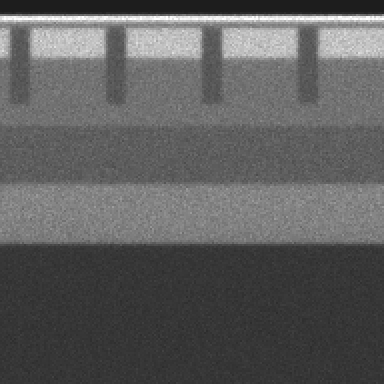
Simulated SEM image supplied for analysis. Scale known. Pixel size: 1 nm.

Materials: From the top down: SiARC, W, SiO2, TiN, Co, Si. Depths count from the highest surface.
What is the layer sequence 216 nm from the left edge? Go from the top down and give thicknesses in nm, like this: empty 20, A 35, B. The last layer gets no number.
SiARC 88, SiO2 22, TiN 58, Co 60, Si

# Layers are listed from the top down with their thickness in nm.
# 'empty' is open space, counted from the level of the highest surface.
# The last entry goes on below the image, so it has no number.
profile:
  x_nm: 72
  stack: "SiARC 12, W 30, SiO2 68, TiN 58, Co 60, Si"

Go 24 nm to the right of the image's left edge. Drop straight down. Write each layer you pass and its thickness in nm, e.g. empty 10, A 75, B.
SiARC 88, SiO2 22, TiN 58, Co 60, Si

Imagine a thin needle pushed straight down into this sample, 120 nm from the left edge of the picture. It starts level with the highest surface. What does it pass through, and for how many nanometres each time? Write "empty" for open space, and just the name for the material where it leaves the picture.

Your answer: SiARC 88, SiO2 22, TiN 58, Co 60, Si